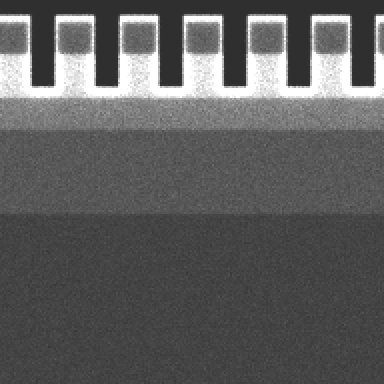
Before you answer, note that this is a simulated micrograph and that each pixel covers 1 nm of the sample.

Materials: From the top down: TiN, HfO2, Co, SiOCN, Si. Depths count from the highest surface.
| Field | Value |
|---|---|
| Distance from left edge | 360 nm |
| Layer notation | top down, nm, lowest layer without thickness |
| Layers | empty 72, HfO2 10, Co 32, SiOCN 84, Si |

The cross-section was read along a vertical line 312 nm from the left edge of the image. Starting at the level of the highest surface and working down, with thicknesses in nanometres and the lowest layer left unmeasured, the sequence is TiN 38, HfO2 44, Co 32, SiOCN 84, Si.